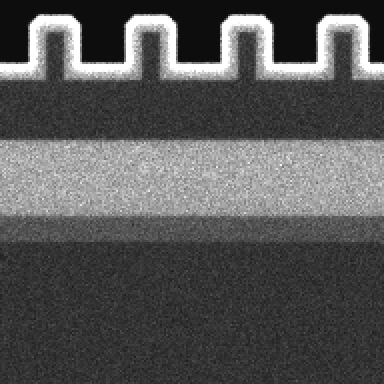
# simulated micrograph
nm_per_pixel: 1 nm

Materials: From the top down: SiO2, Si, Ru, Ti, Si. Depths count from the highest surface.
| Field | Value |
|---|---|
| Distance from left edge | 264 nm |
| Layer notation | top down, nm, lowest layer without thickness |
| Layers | empty 2, SiO2 62, Si 60, Ru 76, Ti 26, Si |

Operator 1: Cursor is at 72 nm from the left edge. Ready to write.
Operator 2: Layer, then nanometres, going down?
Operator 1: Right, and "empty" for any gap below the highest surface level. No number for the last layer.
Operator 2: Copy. empty 2, SiO2 62, Si 60, Ru 76, Ti 26, Si